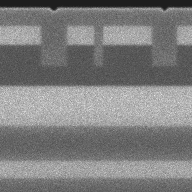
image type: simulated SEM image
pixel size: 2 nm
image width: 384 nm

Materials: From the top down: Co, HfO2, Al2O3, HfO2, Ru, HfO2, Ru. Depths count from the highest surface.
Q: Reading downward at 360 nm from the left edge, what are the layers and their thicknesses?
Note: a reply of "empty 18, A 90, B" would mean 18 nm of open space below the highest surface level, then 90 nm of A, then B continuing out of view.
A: Co 36, HfO2 38, Al2O3 82, HfO2 80, Ru 70, HfO2 34, Ru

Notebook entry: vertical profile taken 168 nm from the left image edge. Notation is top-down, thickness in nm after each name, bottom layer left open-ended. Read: Co 36, HfO2 38, Al2O3 82, HfO2 80, Ru 70, HfO2 34, Ru